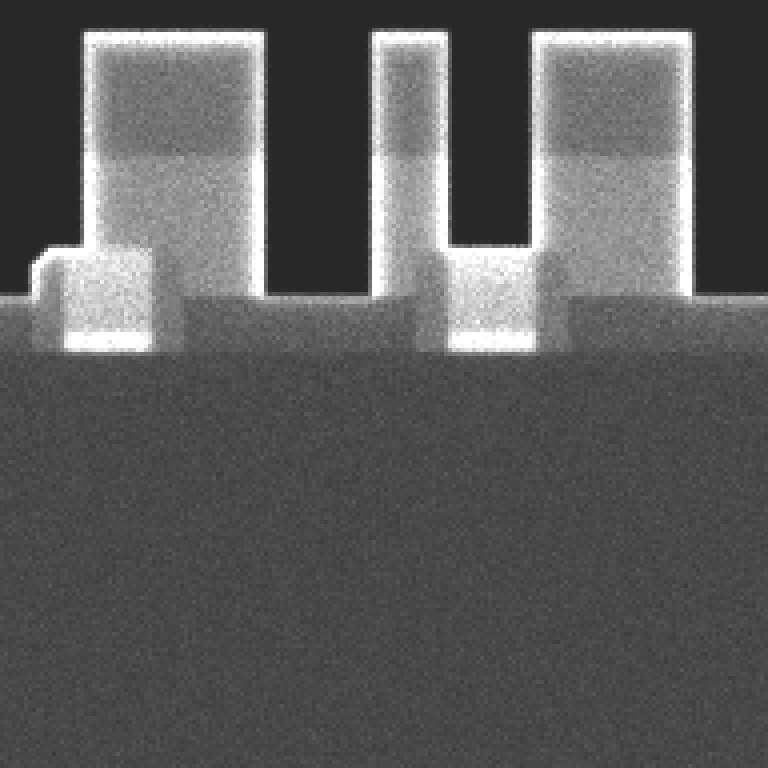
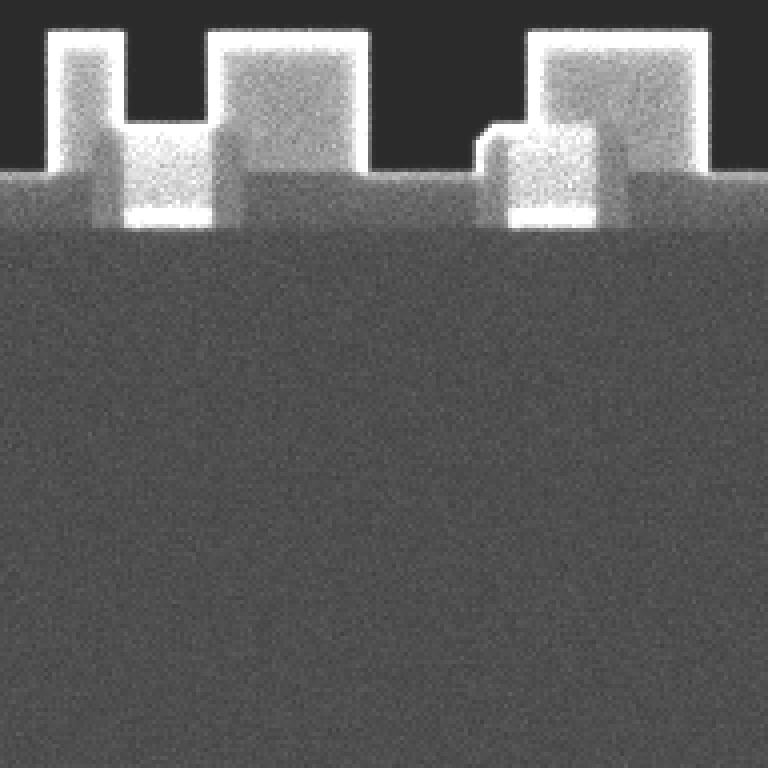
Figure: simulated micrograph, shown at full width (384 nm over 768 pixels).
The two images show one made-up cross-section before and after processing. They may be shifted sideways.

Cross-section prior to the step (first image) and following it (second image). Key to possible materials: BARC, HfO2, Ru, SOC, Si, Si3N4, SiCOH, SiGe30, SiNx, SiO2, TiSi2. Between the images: SOC was removed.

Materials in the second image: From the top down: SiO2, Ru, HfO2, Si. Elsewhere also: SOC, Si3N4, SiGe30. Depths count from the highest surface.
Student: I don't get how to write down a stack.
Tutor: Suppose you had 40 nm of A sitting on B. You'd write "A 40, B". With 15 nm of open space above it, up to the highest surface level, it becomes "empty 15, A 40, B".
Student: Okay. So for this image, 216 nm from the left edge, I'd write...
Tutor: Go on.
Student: empty 70, SiGe30 28, Si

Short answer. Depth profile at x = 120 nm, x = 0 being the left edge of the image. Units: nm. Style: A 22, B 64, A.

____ SiO2 54, Si3N4 44, Si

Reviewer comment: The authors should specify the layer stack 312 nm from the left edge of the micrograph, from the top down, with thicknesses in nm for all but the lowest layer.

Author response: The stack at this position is SiO2 54, Si3N4 44, Si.